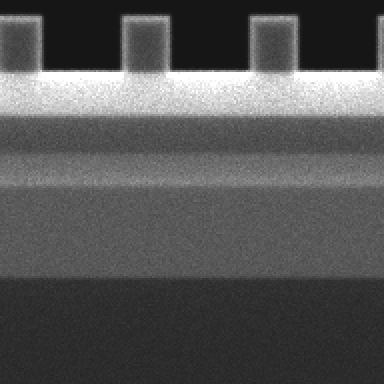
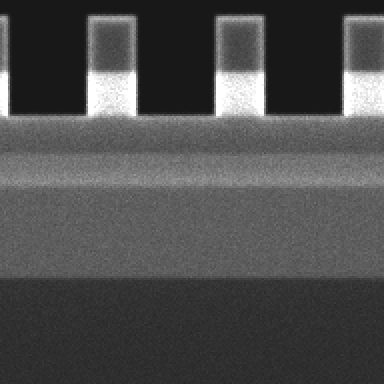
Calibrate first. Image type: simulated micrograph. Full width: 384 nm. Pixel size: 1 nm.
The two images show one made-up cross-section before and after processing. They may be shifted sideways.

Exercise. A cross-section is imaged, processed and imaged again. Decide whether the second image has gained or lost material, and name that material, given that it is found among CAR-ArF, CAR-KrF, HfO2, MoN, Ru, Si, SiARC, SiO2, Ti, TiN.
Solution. removed: HfO2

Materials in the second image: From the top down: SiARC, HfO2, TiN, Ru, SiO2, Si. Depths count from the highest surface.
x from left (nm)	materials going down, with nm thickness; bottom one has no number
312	empty 100, TiN 38, Ru 32, SiO2 92, Si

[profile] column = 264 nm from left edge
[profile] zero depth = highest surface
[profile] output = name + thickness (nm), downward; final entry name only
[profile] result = empty 100, TiN 38, Ru 32, SiO2 92, Si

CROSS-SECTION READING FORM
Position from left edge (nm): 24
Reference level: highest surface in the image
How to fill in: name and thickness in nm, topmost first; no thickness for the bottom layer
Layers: empty 100, TiN 38, Ru 32, SiO2 92, Si